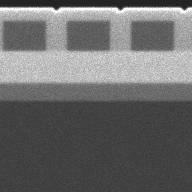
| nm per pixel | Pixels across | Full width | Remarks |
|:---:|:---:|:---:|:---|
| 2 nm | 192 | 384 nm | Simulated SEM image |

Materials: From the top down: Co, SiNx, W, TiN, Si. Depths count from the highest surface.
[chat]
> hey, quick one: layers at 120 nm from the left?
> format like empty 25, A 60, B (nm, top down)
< Co 86, W 64, TiN 36, Si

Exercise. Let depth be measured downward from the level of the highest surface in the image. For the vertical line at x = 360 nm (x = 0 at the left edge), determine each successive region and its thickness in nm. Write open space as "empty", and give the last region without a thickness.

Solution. Co 86, W 64, TiN 36, Si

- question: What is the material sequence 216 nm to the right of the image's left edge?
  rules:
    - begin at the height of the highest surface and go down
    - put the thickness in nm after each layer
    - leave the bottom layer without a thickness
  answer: Co 26, SiNx 60, W 64, TiN 36, Si